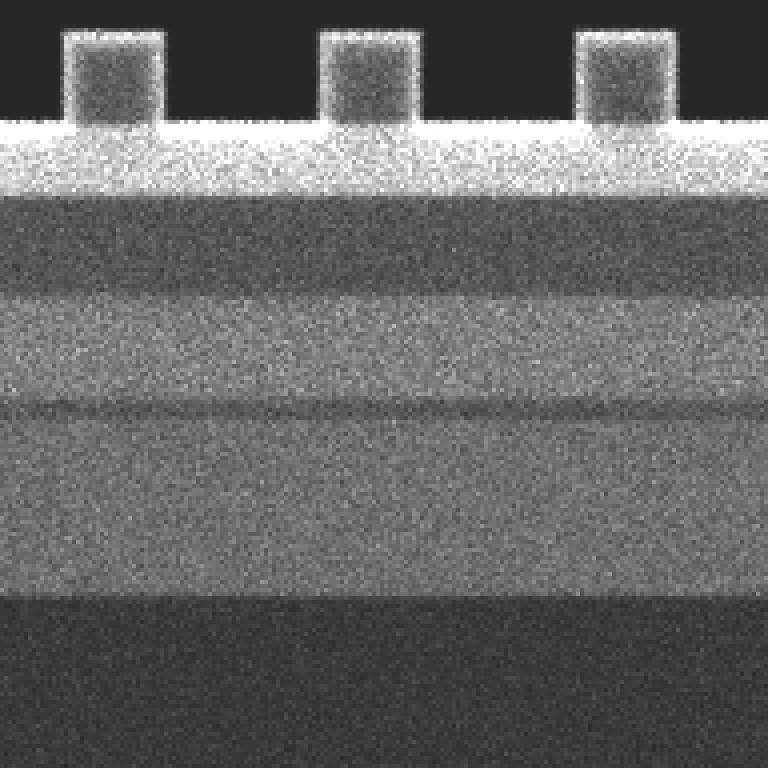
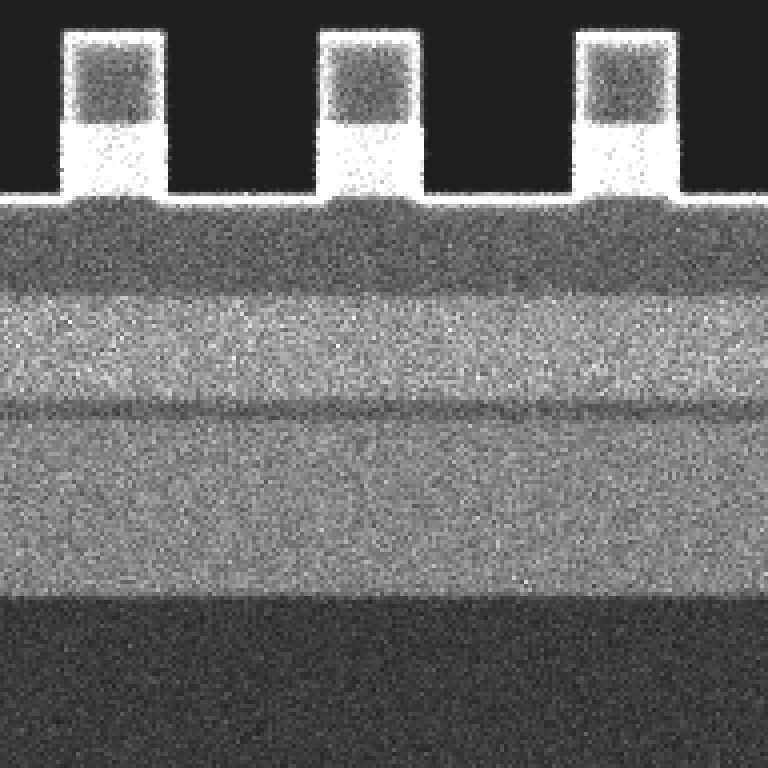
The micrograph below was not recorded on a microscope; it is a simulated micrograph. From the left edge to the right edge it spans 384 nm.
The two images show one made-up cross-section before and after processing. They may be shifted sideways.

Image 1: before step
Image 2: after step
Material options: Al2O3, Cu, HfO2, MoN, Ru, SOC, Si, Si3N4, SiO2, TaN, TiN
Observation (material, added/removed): HfO2, removed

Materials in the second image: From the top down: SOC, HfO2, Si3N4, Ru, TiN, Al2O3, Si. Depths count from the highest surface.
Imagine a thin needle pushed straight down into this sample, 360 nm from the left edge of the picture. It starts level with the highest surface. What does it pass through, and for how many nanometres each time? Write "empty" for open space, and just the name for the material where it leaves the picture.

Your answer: empty 82, Si3N4 50, Ru 52, TiN 10, Al2O3 88, Si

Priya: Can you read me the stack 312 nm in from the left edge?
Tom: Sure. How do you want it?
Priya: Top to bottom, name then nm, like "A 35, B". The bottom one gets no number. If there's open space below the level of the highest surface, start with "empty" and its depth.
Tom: SOC 46, HfO2 36, Si3N4 50, Ru 52, TiN 10, Al2O3 88, Si